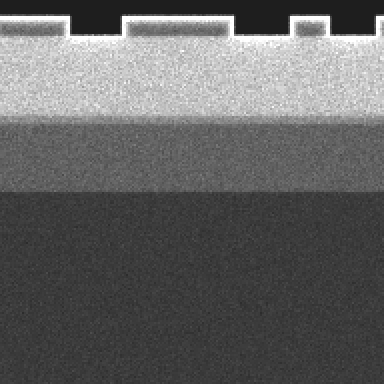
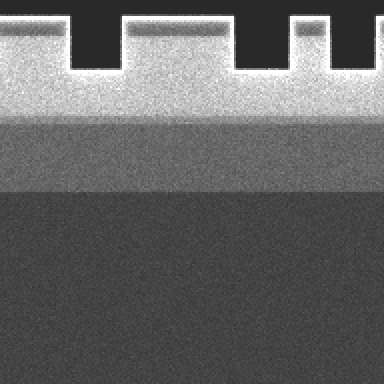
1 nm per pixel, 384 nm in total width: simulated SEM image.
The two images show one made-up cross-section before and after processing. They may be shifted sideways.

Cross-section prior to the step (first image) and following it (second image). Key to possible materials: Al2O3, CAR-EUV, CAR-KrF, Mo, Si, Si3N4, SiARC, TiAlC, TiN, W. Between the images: W was removed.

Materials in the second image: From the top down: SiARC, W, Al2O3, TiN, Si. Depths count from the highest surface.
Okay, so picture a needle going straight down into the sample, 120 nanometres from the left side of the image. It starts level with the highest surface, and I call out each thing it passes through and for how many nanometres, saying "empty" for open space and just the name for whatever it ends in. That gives empty 54, W 46, Al2O3 8, TiN 68, Si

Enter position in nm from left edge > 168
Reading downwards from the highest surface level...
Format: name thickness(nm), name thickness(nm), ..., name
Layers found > SiARC 20, W 80, Al2O3 8, TiN 68, Si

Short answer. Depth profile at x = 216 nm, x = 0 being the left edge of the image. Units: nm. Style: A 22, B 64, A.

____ SiARC 20, W 80, Al2O3 8, TiN 68, Si